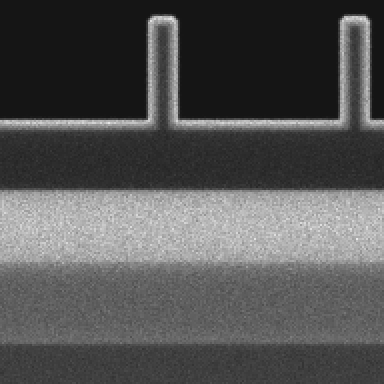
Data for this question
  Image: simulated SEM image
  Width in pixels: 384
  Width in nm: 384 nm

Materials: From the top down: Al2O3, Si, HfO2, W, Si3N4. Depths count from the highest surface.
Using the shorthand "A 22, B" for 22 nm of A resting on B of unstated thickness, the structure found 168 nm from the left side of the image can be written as Al2O3 114, Si 60, HfO2 72, W 82, Si3N4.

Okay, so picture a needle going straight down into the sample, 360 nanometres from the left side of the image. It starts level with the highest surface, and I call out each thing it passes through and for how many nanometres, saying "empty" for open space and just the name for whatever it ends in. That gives Al2O3 114, Si 60, HfO2 72, W 82, Si3N4